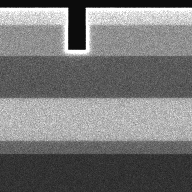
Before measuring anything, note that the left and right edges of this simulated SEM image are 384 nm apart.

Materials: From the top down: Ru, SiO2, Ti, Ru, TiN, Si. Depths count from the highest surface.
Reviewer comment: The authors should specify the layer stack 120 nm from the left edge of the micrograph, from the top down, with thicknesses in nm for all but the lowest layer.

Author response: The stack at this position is Ru 34, SiO2 62, Ti 84, Ru 86, TiN 26, Si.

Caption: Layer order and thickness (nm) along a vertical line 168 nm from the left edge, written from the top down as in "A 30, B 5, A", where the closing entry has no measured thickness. empty 84, SiO2 12, Ti 84, Ru 86, TiN 26, Si